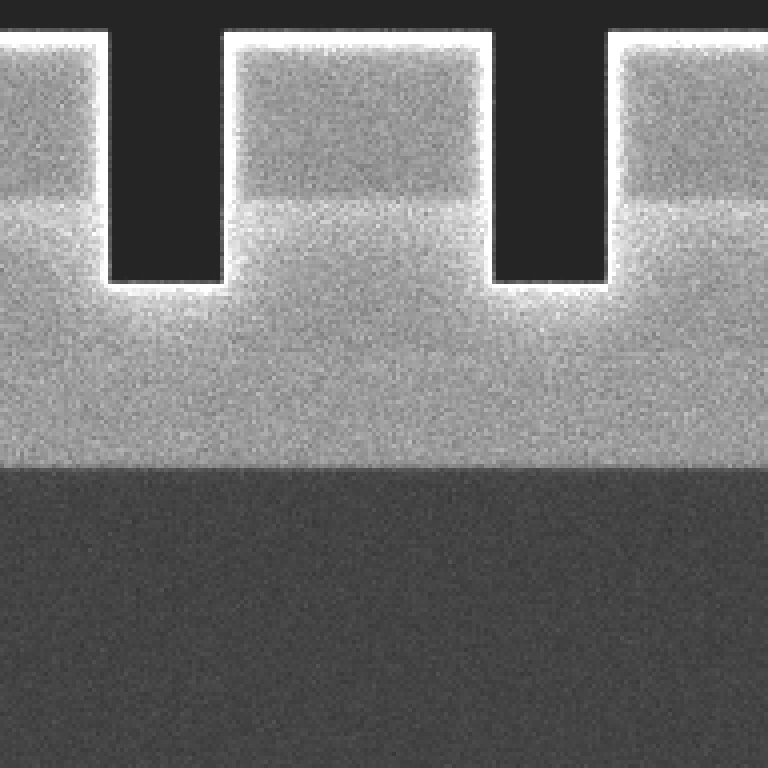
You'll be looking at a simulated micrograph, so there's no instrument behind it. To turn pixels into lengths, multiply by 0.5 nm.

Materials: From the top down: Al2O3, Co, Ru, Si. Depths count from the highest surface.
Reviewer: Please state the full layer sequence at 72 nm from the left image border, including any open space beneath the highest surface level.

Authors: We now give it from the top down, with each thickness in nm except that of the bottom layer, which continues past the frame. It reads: empty 126, Co 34, Ru 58, Si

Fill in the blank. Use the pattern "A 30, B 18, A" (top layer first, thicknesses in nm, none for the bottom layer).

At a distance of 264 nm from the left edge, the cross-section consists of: empty 126, Co 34, Ru 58, Si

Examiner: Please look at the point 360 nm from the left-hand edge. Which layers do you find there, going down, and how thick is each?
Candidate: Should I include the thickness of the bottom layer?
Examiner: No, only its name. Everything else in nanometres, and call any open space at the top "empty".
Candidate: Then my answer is Al2O3 84, Co 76, Ru 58, Si